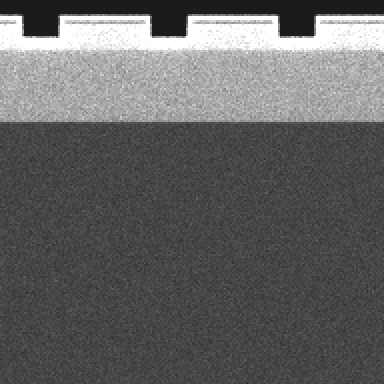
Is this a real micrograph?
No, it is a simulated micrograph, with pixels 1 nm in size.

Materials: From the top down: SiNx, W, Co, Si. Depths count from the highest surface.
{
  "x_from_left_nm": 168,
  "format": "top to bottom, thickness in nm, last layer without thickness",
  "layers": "empty 22, W 12, Co 72, Si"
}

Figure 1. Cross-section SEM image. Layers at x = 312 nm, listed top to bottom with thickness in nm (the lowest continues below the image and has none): empty 22, W 12, Co 72, Si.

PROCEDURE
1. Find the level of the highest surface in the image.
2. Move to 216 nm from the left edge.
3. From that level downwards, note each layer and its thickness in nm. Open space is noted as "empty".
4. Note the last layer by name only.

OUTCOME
SiNx 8, W 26, Co 72, Si